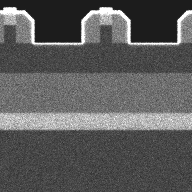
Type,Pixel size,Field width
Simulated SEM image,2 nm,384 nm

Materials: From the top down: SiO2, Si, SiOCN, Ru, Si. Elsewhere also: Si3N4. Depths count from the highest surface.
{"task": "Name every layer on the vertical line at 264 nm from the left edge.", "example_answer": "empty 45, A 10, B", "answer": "empty 70, Si 60, SiOCN 80, Ru 34, Si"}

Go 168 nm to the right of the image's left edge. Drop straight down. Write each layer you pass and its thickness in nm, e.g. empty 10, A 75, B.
empty 20, Si3N4 50, Si 60, SiOCN 80, Ru 34, Si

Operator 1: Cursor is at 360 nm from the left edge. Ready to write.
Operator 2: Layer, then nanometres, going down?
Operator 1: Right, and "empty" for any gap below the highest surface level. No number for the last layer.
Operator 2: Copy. empty 20, Si3N4 50, Si 60, SiOCN 80, Ru 34, Si